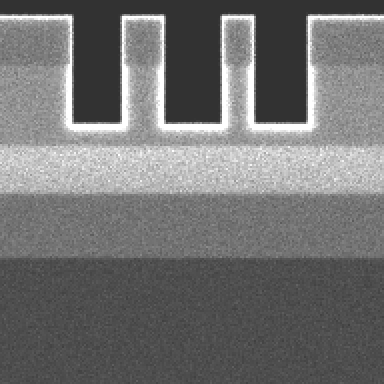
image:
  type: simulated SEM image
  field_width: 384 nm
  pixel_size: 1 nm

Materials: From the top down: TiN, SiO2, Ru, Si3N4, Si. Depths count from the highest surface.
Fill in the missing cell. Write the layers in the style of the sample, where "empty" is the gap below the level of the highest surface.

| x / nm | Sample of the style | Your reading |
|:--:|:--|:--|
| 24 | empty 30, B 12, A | TiN 50, SiO2 80, Ru 48, Si3N4 64, Si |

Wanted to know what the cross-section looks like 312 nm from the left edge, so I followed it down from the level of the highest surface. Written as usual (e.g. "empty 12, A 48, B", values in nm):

TiN 50, SiO2 80, Ru 48, Si3N4 64, Si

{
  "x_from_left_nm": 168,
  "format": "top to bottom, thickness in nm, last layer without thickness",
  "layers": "empty 108, SiO2 22, Ru 48, Si3N4 64, Si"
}